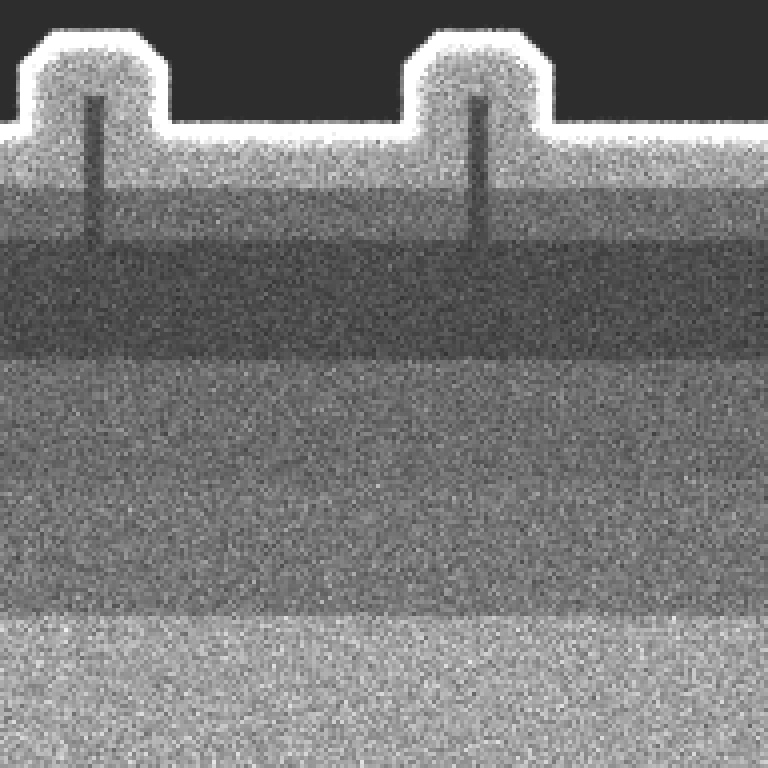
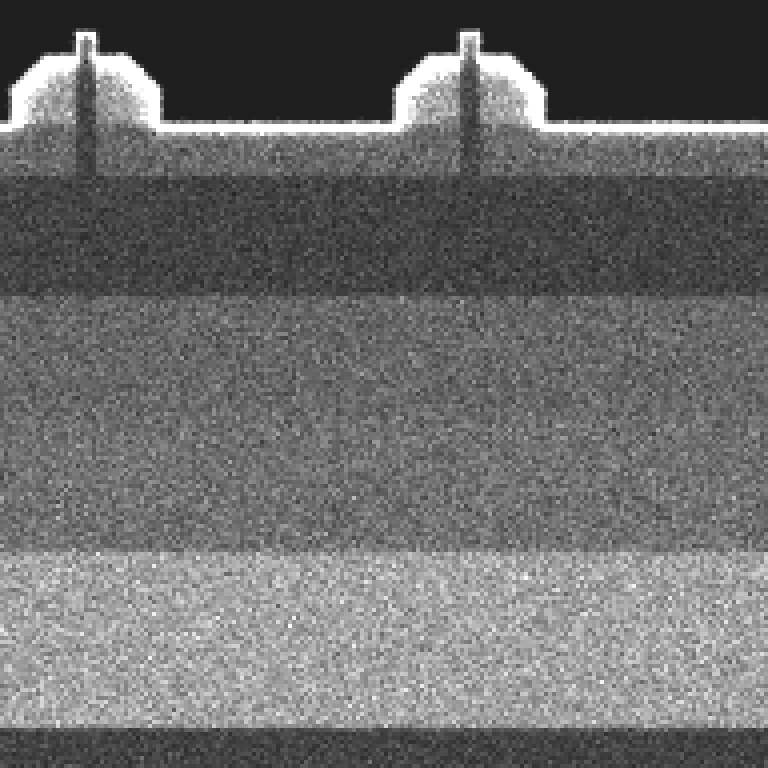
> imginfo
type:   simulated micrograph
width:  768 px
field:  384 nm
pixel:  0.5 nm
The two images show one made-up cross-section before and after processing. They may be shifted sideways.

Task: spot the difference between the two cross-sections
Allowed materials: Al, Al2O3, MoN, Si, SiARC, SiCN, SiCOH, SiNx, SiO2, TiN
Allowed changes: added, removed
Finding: removed SiO2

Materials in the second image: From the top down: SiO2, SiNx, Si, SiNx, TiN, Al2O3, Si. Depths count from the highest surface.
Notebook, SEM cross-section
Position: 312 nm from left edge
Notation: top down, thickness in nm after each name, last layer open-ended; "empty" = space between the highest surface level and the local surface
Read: empty 46, SiNx 26, Si 60, SiNx 60, TiN 68, Al2O3 88, Si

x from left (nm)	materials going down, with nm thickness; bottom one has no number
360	empty 46, SiNx 26, Si 60, SiNx 60, TiN 68, Al2O3 88, Si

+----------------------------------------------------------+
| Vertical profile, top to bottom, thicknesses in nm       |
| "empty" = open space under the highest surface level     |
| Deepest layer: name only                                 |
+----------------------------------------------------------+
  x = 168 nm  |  empty 46, SiNx 26, Si 60, SiNx 60, TiN 68, Al2O3 88, Si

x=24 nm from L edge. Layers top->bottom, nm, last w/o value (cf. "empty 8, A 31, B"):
empty 12, SiO2 34, SiNx 26, Si 60, SiNx 60, TiN 68, Al2O3 88, Si